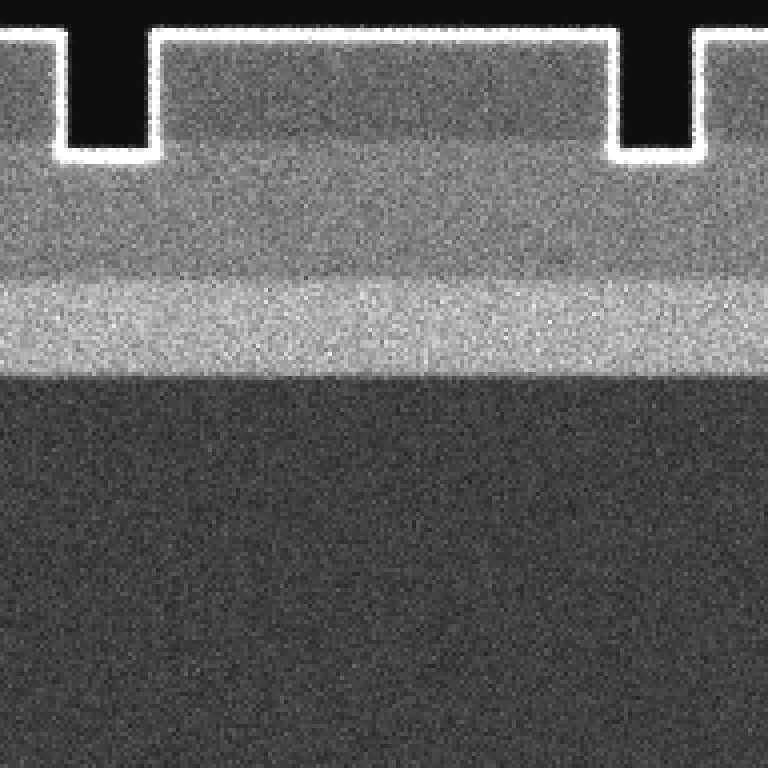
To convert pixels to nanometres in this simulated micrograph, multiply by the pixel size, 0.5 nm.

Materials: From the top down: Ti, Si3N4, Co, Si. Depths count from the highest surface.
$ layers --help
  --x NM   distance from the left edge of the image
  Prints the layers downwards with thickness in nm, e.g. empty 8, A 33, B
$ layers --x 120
Ti 54, Si3N4 70, Co 48, Si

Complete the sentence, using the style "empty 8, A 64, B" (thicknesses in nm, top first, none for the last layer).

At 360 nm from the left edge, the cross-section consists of Ti 54, Si3N4 70, Co 48, Si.